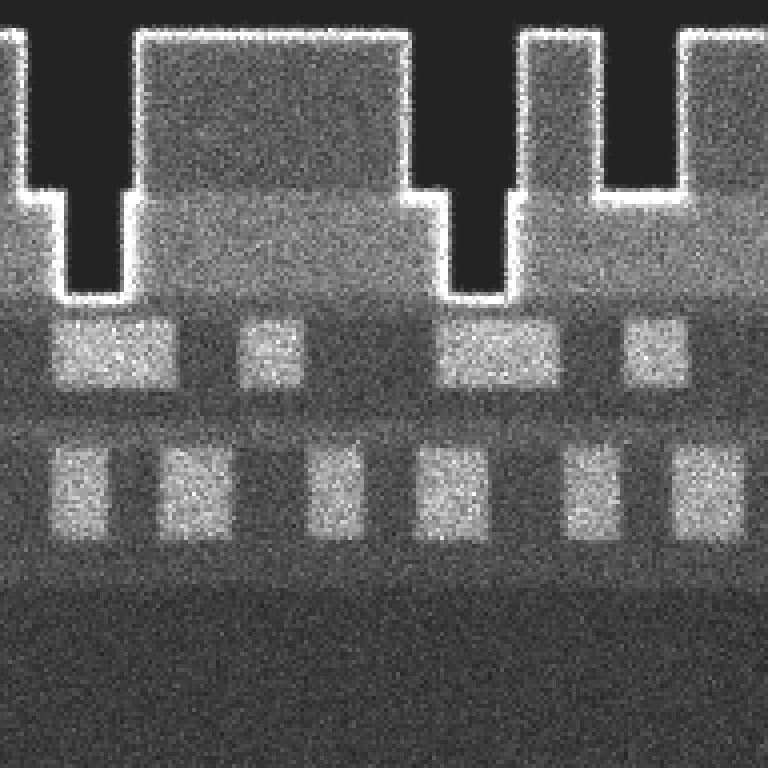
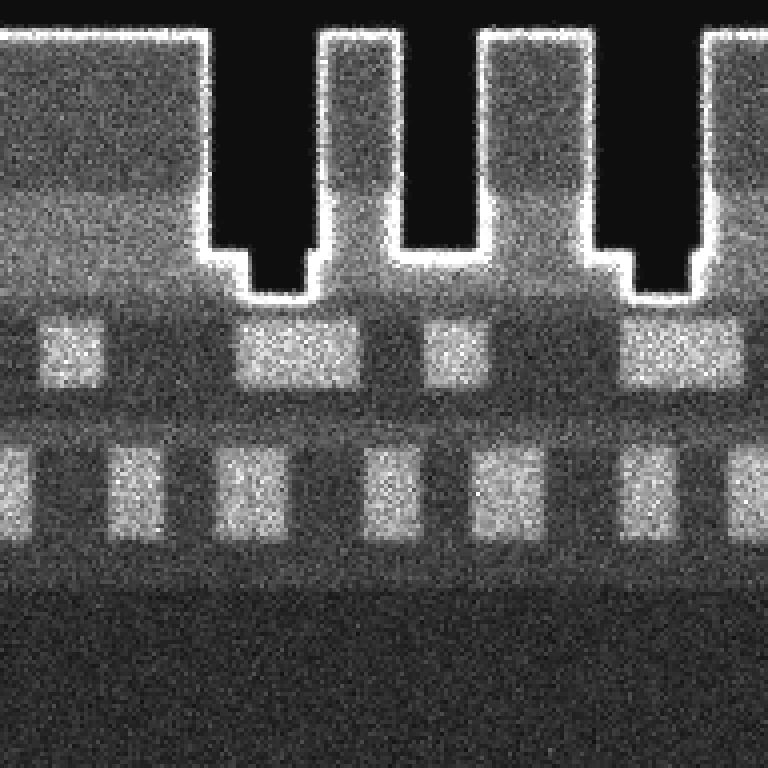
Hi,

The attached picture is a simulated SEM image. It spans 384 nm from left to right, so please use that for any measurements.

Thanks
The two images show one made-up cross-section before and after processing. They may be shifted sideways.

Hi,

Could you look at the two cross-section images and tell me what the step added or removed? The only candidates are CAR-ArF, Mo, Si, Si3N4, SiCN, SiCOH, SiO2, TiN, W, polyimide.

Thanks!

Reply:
removed SiO2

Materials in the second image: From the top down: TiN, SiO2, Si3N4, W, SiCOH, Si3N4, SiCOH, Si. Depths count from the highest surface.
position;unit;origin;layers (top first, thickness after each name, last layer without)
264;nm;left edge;TiN 80, SiO2 52, Si3N4 12, SiCOH 50, Si3N4 14, W 46, SiCOH 24, Si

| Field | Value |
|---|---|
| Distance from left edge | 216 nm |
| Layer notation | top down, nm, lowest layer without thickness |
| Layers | empty 110, SiO2 22, Si3N4 12, W 34, SiCOH 16, Si3N4 14, SiCOH 70, Si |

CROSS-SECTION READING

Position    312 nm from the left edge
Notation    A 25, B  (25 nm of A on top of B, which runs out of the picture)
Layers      empty 110, SiO2 22, Si3N4 12, W 34, SiCOH 16, Si3N4 14, W 46, SiCOH 24, Si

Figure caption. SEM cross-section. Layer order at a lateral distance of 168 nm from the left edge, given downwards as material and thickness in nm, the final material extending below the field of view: TiN 80, SiO2 52, Si3N4 12, W 34, SiCOH 16, Si3N4 14, SiCOH 70, Si